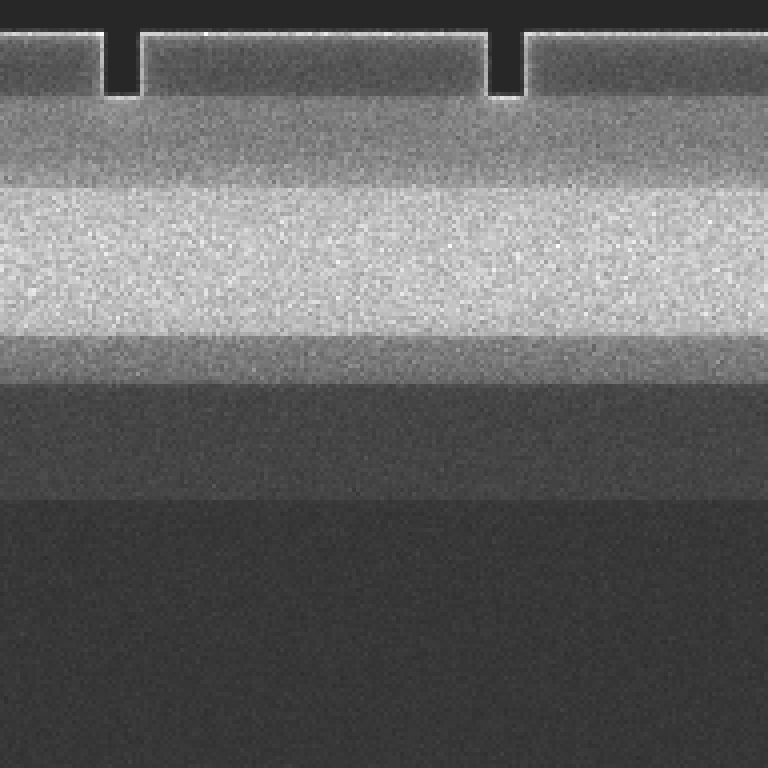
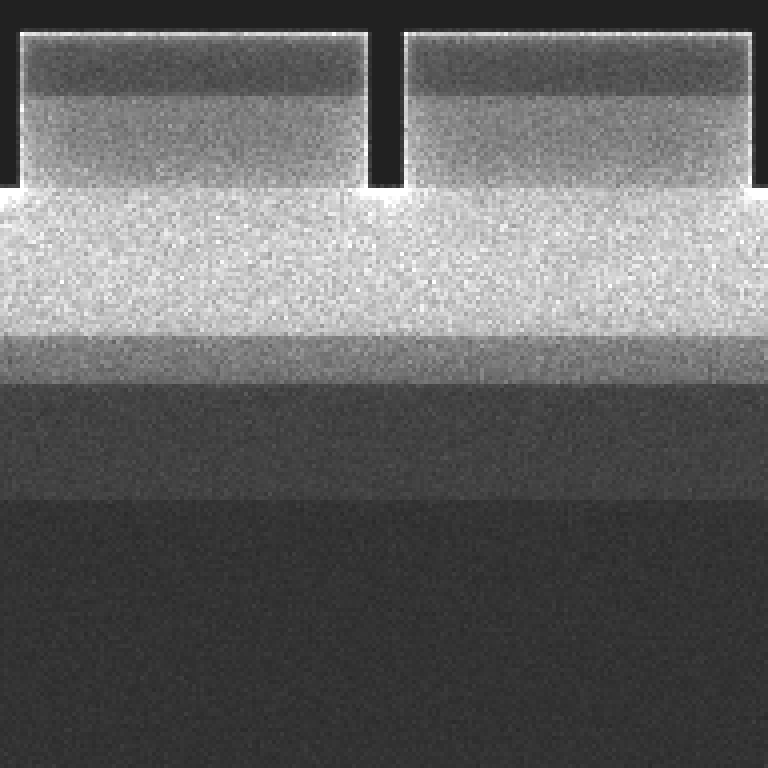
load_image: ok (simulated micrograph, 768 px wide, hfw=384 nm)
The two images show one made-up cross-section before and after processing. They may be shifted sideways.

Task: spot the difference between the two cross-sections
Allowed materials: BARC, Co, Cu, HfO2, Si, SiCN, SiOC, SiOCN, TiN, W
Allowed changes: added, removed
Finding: removed W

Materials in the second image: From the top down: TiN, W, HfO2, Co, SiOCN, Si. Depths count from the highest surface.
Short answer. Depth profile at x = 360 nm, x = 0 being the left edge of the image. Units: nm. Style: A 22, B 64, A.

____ TiN 32, W 46, HfO2 74, Co 24, SiOCN 58, Si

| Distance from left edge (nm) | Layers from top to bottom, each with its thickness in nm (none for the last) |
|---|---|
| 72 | TiN 32, W 46, HfO2 74, Co 24, SiOCN 58, Si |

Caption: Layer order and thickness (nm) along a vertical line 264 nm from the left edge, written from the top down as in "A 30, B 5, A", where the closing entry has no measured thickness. TiN 32, W 46, HfO2 74, Co 24, SiOCN 58, Si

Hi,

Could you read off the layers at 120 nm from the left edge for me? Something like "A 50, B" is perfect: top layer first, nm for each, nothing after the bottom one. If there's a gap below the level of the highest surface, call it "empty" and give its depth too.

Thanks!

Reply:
TiN 32, W 46, HfO2 74, Co 24, SiOCN 58, Si